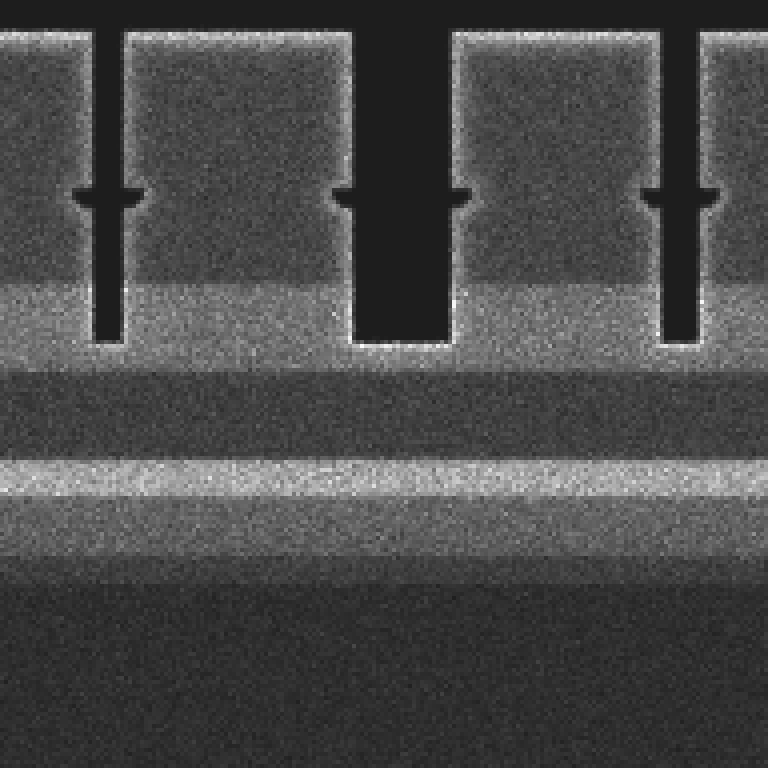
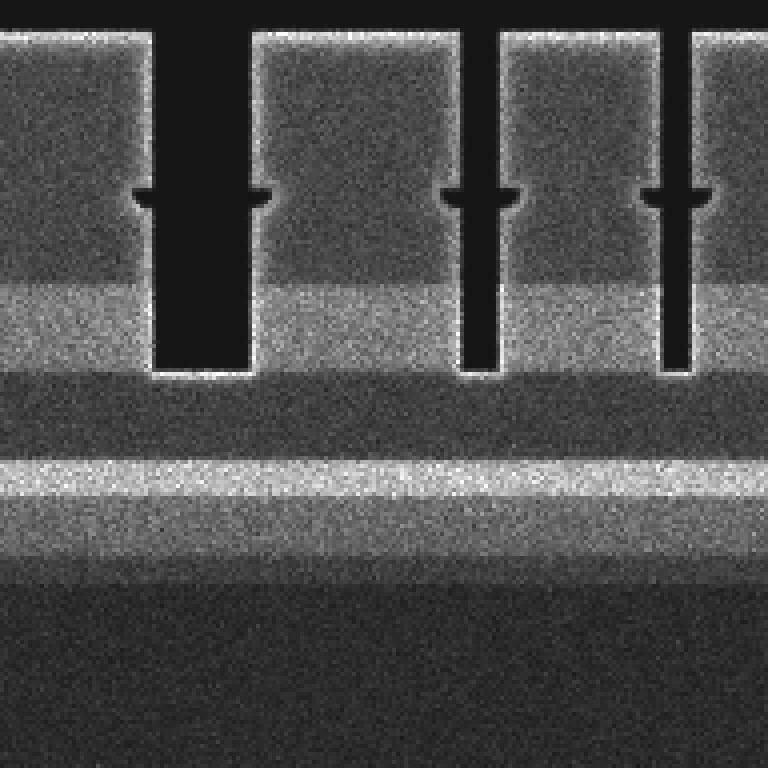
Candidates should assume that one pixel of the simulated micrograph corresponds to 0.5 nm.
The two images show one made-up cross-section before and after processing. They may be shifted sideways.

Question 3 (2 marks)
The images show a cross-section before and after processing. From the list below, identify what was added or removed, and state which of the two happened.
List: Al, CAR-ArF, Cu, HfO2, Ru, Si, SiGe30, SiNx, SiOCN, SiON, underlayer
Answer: Ru was removed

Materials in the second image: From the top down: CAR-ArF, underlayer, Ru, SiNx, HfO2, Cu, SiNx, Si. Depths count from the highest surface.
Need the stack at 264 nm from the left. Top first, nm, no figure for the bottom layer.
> CAR-ArF 78, underlayer 48, Ru 44, SiNx 44, HfO2 18, Cu 30, SiNx 14, Si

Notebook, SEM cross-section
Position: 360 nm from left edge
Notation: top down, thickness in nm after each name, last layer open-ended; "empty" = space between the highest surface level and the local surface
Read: CAR-ArF 78, underlayer 48, Ru 44, SiNx 44, HfO2 18, Cu 30, SiNx 14, Si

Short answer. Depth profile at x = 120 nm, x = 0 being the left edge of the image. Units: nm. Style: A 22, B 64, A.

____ empty 170, SiNx 44, HfO2 18, Cu 30, SiNx 14, Si